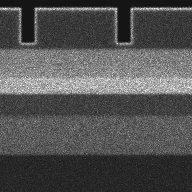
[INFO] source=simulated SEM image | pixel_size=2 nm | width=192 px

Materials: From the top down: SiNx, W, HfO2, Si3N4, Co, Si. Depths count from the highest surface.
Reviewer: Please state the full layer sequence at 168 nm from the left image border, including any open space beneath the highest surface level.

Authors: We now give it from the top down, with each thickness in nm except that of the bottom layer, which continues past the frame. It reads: SiNx 82, W 58, HfO2 32, Si3N4 44, Co 78, Si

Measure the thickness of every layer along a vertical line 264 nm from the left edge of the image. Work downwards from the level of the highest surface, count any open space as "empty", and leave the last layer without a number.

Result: SiNx 82, W 58, HfO2 32, Si3N4 44, Co 78, Si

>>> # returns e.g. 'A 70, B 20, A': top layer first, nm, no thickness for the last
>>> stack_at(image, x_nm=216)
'SiNx 82, W 58, HfO2 32, Si3N4 44, Co 78, Si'